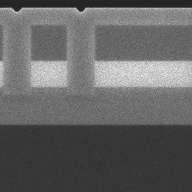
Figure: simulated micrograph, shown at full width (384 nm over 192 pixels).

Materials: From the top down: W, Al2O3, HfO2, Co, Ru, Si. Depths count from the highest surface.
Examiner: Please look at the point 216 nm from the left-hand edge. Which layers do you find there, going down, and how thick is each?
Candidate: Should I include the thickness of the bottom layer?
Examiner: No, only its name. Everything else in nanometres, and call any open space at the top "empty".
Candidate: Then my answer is W 34, Al2O3 72, HfO2 52, Co 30, Ru 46, Si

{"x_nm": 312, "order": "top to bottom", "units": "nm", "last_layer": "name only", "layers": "W 34, Al2O3 72, HfO2 52, Co 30, Ru 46, Si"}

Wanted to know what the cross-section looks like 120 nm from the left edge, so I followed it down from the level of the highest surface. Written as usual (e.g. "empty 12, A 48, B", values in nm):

W 34, Al2O3 72, HfO2 52, Co 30, Ru 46, Si